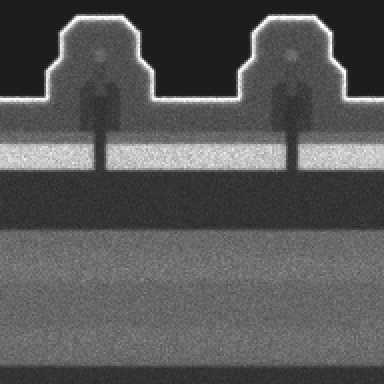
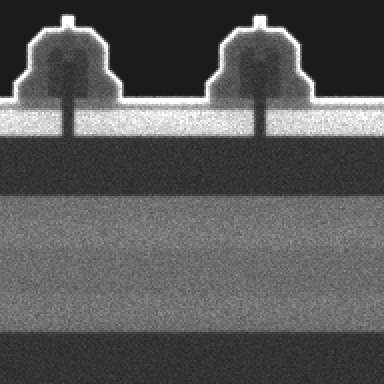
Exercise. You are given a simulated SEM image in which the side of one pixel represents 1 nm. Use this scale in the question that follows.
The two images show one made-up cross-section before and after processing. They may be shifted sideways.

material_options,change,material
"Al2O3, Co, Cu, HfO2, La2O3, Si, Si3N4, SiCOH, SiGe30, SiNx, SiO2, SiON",removed,Si3N4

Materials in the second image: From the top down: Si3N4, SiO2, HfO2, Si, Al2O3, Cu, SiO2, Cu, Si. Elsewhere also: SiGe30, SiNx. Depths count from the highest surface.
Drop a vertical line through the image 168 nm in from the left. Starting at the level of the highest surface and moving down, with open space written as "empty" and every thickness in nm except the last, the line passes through empty 82, SiO2 12, HfO2 26, Si 60, Al2O3 24, Cu 28, SiO2 46, Cu 38, Si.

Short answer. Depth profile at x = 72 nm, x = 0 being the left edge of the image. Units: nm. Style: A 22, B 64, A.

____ SiO2 12, SiNx 34, Si 134, Al2O3 24, Cu 28, SiO2 46, Cu 38, Si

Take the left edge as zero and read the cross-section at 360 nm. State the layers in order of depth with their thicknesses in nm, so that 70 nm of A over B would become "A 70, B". empty 82, SiO2 12, HfO2 26, Si 60, Al2O3 24, Cu 28, SiO2 46, Cu 38, Si